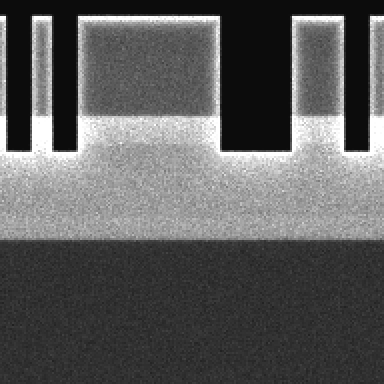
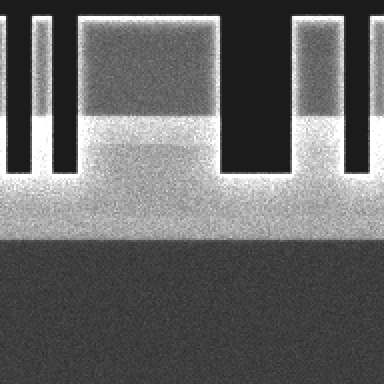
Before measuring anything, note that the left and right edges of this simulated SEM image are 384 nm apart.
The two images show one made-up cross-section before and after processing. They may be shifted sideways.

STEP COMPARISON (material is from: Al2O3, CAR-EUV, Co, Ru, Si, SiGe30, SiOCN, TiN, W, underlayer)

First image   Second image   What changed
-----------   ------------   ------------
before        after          Co, removed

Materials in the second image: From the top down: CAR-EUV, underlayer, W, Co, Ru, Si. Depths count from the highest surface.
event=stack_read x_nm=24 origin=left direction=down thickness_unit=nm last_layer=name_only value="empty 158, Co 42, Ru 24, Si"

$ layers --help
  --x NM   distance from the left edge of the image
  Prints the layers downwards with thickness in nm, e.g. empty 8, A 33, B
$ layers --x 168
CAR-EUV 40, underlayer 60, W 28, Co 72, Ru 24, Si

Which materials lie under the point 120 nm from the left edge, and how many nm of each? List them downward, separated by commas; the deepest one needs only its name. CAR-EUV 40, underlayer 60, W 28, Co 72, Ru 24, Si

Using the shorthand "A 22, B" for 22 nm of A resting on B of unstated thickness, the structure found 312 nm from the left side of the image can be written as CAR-EUV 40, underlayer 60, W 28, Co 72, Ru 24, Si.